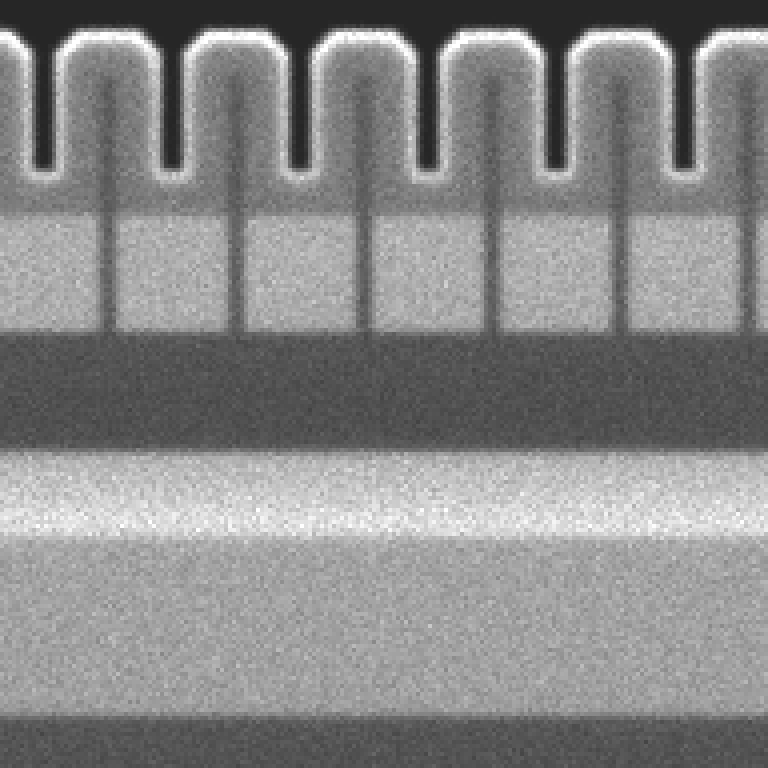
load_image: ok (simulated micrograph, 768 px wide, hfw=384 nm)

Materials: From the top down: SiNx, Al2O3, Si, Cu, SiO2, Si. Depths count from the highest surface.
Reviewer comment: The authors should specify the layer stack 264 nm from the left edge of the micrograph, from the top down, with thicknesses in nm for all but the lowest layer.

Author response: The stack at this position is empty 4, SiNx 88, Al2O3 58, Si 60, Cu 42, SiO2 90, Si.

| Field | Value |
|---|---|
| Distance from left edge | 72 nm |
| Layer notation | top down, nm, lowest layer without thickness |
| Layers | empty 4, SiNx 88, Al2O3 58, Si 60, Cu 42, SiO2 90, Si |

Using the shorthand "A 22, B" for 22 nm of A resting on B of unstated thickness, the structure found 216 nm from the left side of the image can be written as empty 70, SiNx 22, Al2O3 58, Si 60, Cu 42, SiO2 90, Si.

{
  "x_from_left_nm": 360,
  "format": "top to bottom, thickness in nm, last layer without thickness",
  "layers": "SiNx 92, Al2O3 58, Si 60, Cu 42, SiO2 90, Si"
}